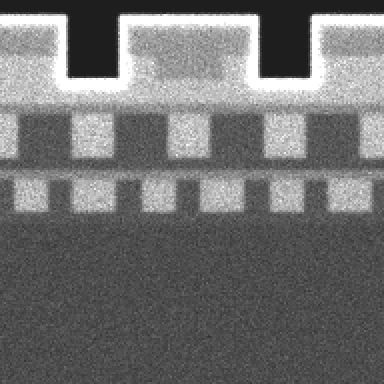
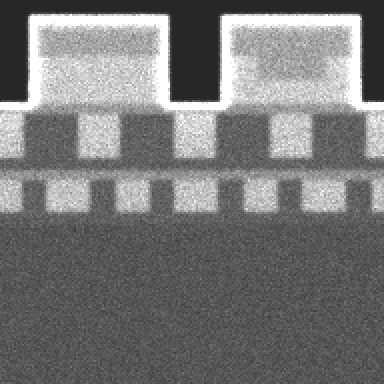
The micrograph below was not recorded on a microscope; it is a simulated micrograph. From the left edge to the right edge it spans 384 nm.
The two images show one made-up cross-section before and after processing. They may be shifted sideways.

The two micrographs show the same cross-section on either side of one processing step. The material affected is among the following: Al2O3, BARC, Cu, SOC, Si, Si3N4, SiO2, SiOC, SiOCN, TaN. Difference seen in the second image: SiO2 removed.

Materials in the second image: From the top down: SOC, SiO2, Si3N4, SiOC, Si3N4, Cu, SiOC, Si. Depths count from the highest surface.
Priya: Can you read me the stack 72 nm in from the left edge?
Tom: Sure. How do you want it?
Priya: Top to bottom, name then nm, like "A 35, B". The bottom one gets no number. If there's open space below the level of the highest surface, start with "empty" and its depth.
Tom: SOC 40, SiO2 48, Si3N4 10, SiOC 56, Si3N4 10, Cu 32, SiOC 12, Si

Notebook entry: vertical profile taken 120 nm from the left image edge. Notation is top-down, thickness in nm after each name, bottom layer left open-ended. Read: SOC 40, SiO2 48, Si3N4 10, SiOC 56, Si3N4 10, Cu 32, SiOC 12, Si